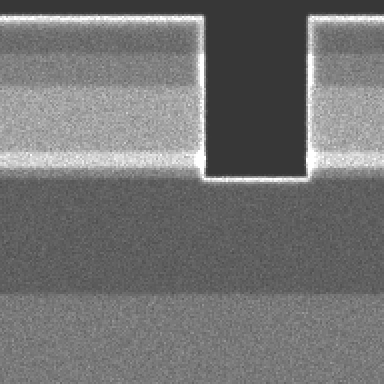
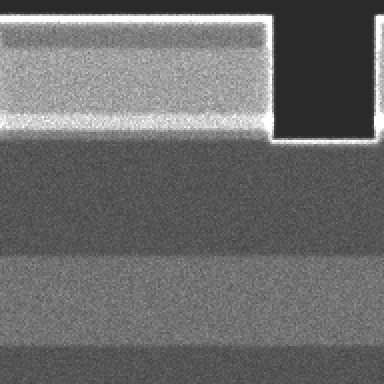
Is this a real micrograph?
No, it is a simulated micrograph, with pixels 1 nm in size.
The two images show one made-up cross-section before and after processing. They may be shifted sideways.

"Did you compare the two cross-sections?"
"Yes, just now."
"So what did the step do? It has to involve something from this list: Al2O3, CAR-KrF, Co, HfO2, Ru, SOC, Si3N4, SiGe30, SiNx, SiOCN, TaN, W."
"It removed SOC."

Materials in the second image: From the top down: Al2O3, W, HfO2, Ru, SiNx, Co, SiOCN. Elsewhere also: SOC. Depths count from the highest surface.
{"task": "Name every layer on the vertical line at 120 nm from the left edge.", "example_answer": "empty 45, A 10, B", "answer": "Al2O3 32, W 66, HfO2 16, Ru 10, SiNx 116, Co 90, SiOCN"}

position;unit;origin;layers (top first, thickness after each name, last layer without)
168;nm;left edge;Al2O3 32, W 66, HfO2 16, Ru 10, SiNx 116, Co 90, SiOCN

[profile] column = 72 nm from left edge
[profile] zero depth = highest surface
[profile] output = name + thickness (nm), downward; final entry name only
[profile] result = Al2O3 32, W 66, HfO2 16, Ru 10, SiNx 116, Co 90, SiOCN